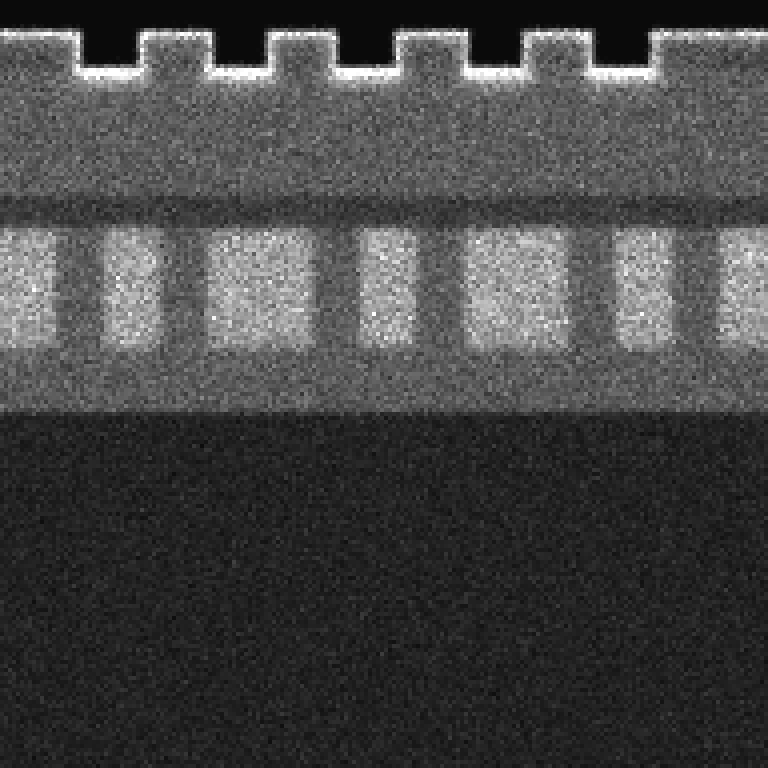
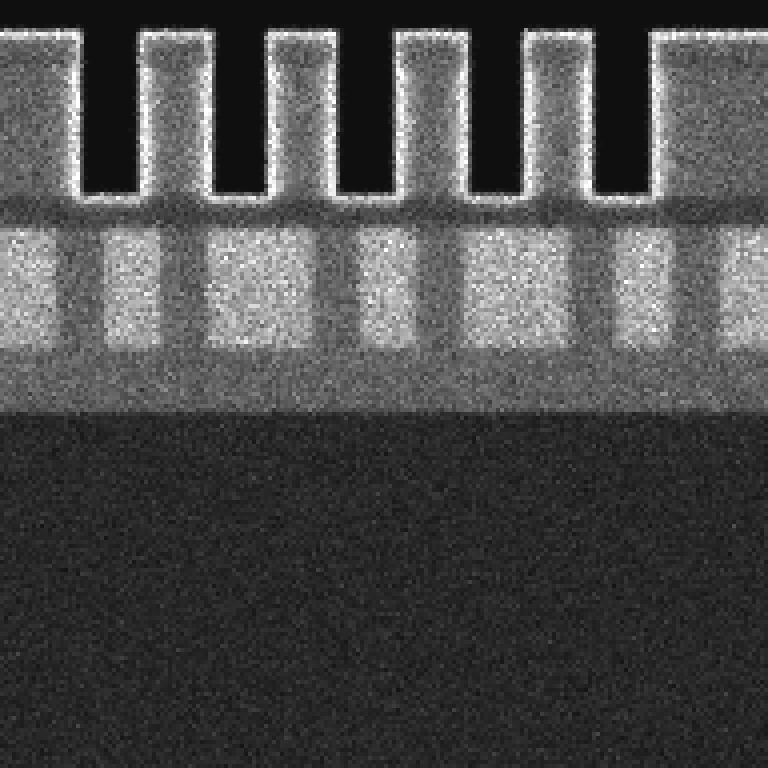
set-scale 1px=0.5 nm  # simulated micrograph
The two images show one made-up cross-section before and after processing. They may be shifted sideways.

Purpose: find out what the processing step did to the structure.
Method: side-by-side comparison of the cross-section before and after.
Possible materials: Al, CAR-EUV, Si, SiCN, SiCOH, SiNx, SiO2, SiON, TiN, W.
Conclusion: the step removed SiO2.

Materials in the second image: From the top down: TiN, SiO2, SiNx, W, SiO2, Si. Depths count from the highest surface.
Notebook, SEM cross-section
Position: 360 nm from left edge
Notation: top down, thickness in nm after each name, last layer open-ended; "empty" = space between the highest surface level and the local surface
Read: TiN 18, SiO2 64, SiNx 16, W 60, SiO2 32, Si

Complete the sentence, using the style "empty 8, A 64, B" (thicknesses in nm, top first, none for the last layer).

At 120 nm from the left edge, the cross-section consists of empty 82, SiNx 16, W 60, SiO2 32, Si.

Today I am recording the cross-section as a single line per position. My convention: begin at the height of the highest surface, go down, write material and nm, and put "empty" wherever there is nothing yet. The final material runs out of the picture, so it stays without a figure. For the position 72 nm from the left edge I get TiN 18, SiO2 64, SiNx 16, W 60, SiO2 32, Si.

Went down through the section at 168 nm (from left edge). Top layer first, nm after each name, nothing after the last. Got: empty 82, SiNx 16, SiO2 92, Si